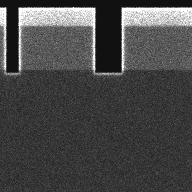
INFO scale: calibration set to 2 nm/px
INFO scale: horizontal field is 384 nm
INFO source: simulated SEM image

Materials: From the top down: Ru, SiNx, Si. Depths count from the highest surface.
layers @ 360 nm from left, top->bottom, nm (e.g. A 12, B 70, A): Ru 36, SiNx 88, Si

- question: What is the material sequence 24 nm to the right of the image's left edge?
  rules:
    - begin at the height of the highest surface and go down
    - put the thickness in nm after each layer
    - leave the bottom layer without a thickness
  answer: empty 130, Si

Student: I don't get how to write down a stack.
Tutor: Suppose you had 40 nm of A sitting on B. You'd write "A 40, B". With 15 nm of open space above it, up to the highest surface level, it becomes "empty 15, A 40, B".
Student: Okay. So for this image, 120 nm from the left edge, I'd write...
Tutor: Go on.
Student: Ru 36, SiNx 88, Si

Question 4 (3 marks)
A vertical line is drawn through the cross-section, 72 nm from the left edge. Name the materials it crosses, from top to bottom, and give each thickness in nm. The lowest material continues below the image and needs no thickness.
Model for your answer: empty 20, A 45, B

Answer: Ru 36, SiNx 88, Si